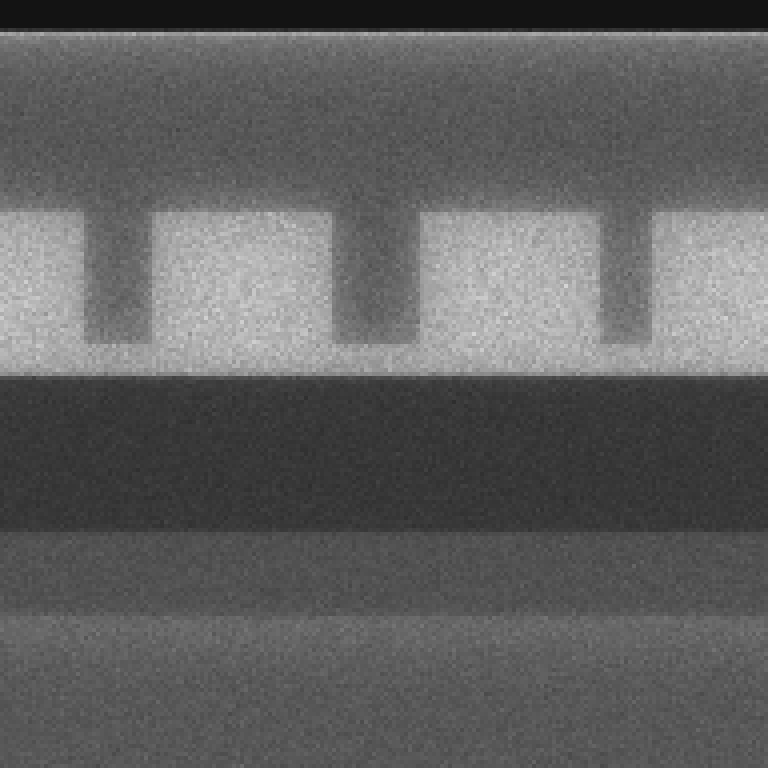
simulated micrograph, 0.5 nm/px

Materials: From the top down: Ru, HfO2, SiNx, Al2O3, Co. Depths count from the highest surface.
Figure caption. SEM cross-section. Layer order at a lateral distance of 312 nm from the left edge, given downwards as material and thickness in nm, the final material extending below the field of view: Ru 156, HfO2 16, SiNx 78, Al2O3 42, Co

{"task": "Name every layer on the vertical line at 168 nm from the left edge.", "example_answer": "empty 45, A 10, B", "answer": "Ru 156, HfO2 16, SiNx 78, Al2O3 42, Co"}